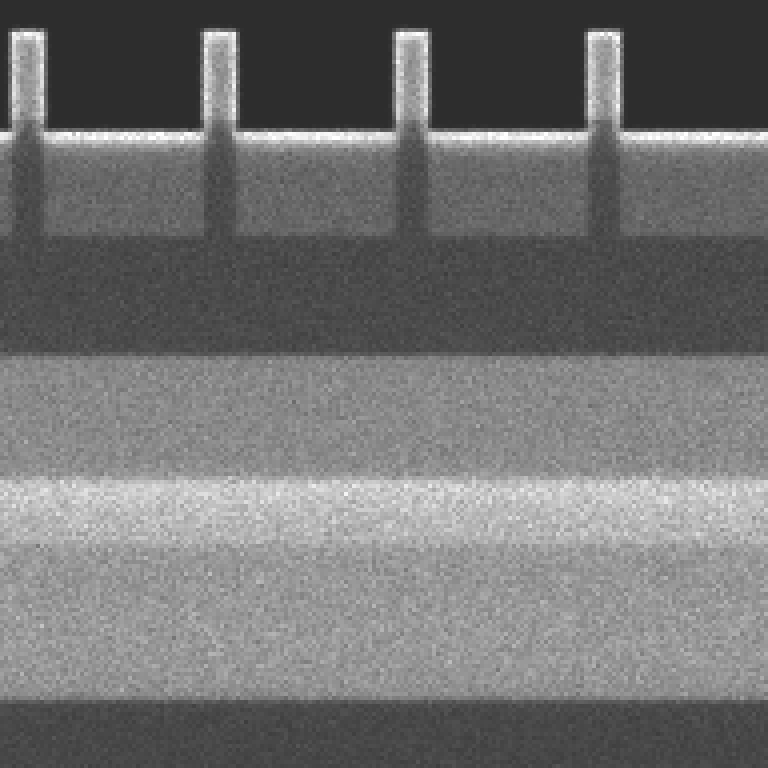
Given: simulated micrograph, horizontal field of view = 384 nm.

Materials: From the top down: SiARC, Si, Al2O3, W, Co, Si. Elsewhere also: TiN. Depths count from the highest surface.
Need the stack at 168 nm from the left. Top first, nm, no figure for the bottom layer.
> empty 50, SiARC 52, Si 60, Al2O3 62, W 32, Co 78, Si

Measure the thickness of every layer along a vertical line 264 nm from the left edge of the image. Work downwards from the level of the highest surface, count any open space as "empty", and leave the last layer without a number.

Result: empty 50, SiARC 52, Si 60, Al2O3 62, W 32, Co 78, Si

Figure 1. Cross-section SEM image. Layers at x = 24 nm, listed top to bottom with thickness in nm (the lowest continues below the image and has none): empty 50, SiARC 52, Si 60, Al2O3 62, W 32, Co 78, Si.